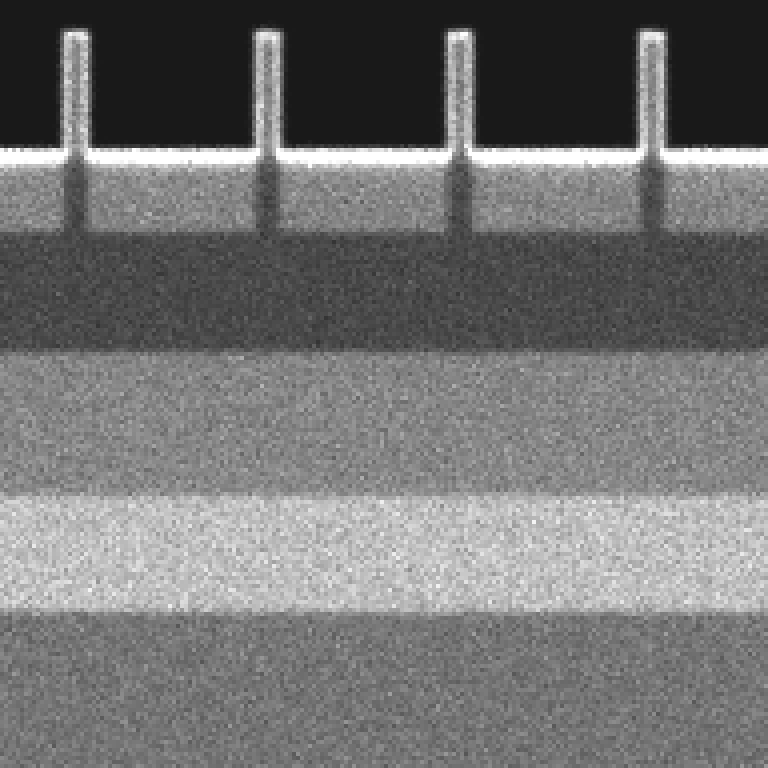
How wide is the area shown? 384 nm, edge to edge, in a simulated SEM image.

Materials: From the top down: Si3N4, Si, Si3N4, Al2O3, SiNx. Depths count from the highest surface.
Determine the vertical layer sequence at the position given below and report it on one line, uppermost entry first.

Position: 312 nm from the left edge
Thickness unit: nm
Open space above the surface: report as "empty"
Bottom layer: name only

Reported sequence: empty 60, Si3N4 40, Si 60, Si3N4 72, Al2O3 58, SiNx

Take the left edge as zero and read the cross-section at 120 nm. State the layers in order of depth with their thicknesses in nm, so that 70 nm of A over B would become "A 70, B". empty 60, Si3N4 40, Si 60, Si3N4 72, Al2O3 58, SiNx